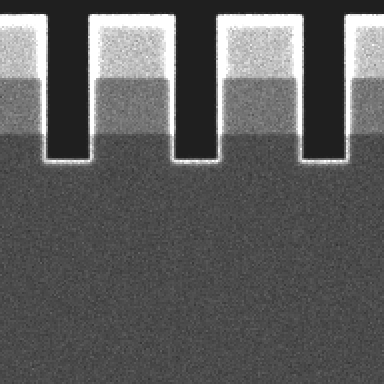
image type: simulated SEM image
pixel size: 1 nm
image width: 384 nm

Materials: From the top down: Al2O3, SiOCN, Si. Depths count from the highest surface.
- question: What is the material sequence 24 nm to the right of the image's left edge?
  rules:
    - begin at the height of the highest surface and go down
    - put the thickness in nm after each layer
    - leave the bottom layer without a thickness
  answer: Al2O3 62, SiOCN 56, Si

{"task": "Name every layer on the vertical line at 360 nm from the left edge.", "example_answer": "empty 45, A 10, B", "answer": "Al2O3 62, SiOCN 56, Si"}